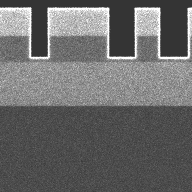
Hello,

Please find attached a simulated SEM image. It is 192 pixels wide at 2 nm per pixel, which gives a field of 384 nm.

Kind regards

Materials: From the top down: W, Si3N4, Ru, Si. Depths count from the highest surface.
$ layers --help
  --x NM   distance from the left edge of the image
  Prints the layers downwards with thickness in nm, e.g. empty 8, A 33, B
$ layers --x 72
empty 98, Si3N4 10, Ru 88, Si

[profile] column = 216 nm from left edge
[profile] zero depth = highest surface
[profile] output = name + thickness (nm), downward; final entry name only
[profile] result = W 56, Si3N4 52, Ru 88, Si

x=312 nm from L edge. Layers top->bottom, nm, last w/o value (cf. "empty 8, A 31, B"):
W 56, Si3N4 52, Ru 88, Si